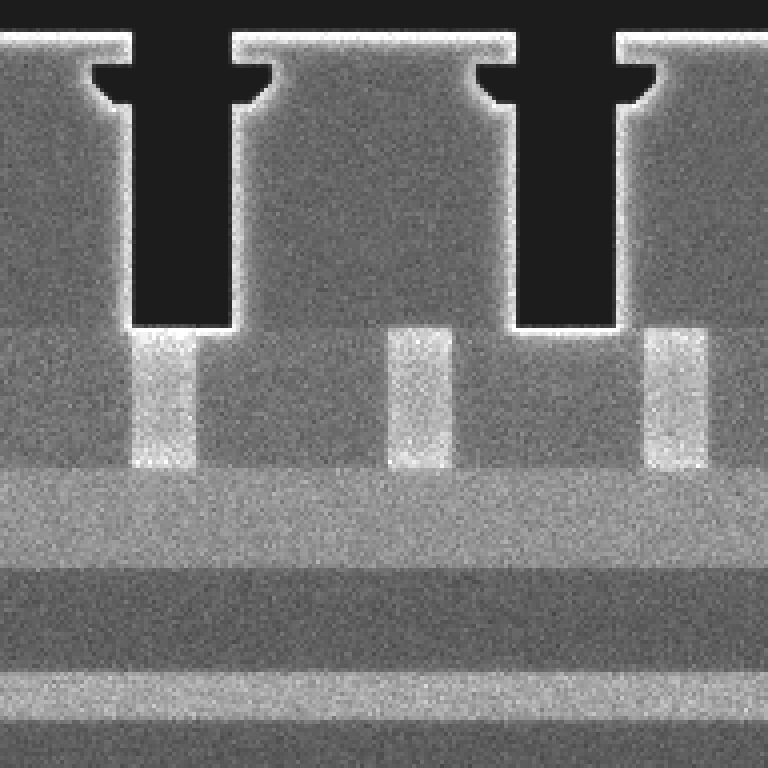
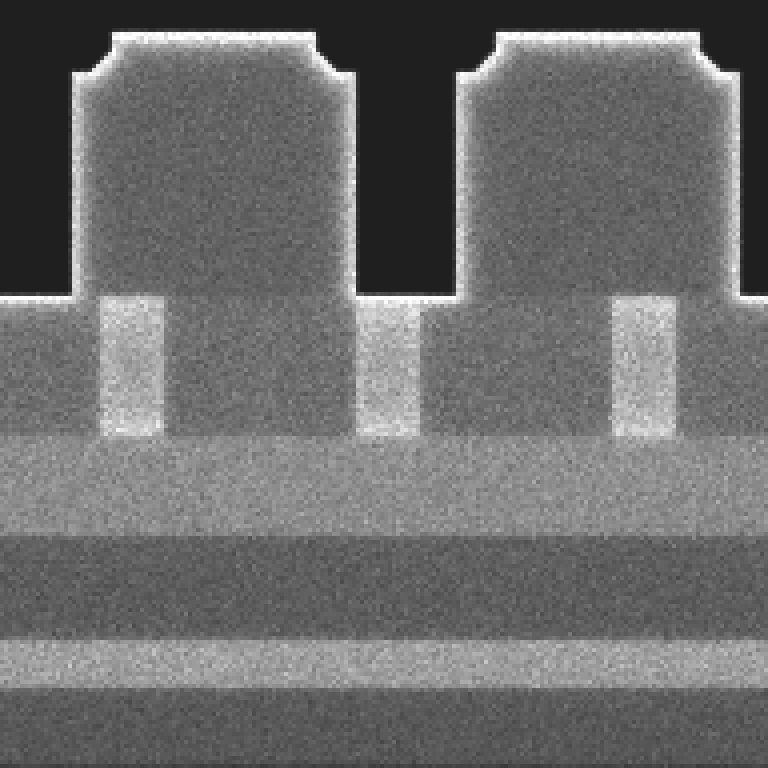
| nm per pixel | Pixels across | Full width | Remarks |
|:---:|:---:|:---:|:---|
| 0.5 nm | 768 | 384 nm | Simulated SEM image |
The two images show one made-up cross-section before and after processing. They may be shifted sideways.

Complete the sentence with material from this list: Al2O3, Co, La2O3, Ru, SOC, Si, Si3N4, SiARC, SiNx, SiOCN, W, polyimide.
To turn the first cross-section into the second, SiARC must be removed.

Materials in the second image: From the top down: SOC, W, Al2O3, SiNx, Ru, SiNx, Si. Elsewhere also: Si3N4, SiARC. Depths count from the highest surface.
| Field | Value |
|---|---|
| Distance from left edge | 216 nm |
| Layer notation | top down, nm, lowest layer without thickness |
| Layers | empty 132, Si3N4 70, Al2O3 50, SiNx 52, Ru 24, SiNx 38, Si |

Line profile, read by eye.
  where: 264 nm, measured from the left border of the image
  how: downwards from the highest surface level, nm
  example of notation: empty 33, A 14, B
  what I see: SOC 132, Si3N4 70, Al2O3 50, SiNx 52, Ru 24, SiNx 38, Si